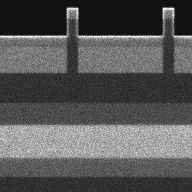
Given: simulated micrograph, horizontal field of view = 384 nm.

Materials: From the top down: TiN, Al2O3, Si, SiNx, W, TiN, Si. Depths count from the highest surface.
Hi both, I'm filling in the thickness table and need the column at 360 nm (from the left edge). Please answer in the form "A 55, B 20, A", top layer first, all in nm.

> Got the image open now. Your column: empty 56, TiN 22, Al2O3 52, Si 60, SiNx 44, W 66, TiN 38, Si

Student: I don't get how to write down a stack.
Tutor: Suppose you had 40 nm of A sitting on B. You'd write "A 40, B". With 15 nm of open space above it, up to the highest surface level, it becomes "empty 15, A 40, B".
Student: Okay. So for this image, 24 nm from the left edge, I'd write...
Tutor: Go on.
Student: empty 56, TiN 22, Al2O3 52, Si 60, SiNx 44, W 66, TiN 38, Si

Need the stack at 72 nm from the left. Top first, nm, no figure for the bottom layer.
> empty 56, TiN 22, Al2O3 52, Si 60, SiNx 44, W 66, TiN 38, Si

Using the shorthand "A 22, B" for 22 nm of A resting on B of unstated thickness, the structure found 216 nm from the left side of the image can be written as empty 56, TiN 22, Al2O3 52, Si 60, SiNx 44, W 66, TiN 38, Si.